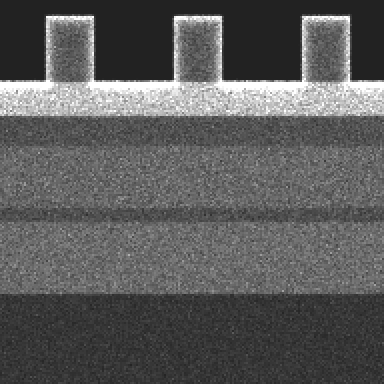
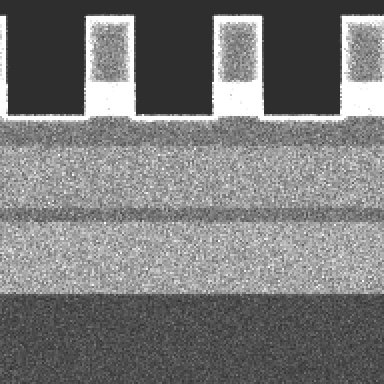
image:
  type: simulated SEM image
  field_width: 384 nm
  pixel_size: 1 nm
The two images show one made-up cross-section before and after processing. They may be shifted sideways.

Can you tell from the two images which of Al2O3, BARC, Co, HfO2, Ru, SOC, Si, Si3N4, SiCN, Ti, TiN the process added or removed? Yes, it removed HfO2.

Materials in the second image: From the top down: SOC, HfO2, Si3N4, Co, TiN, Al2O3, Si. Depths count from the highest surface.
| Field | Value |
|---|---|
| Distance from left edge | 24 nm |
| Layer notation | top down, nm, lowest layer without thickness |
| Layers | empty 100, Si3N4 30, Co 62, TiN 14, Al2O3 72, Si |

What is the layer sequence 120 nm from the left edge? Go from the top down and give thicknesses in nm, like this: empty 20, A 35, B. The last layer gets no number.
SOC 66, HfO2 34, Si3N4 30, Co 62, TiN 14, Al2O3 72, Si